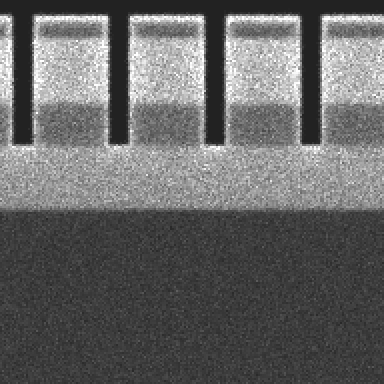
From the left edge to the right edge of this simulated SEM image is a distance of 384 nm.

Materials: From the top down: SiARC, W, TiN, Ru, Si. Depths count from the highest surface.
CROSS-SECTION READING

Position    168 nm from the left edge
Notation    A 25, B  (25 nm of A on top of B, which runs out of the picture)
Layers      SiARC 22, W 66, TiN 42, Ru 64, Si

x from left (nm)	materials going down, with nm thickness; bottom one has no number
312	empty 130, Ru 64, Si